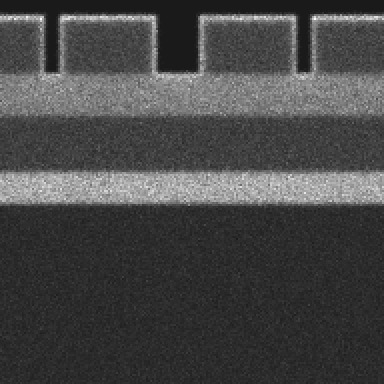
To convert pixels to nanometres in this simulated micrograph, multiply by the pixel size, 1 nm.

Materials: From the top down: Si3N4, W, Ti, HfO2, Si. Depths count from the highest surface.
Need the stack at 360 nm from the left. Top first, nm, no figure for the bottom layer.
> Si3N4 58, W 42, Ti 56, HfO2 32, Si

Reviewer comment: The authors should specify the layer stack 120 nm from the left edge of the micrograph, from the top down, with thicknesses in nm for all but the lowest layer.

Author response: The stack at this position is Si3N4 58, W 42, Ti 56, HfO2 32, Si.